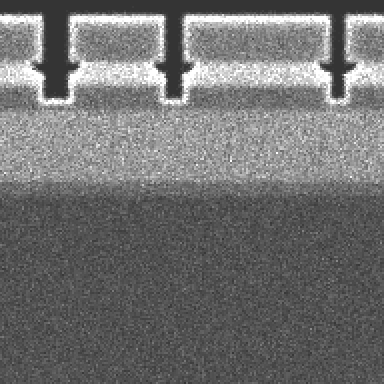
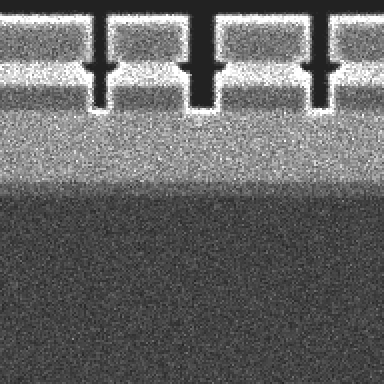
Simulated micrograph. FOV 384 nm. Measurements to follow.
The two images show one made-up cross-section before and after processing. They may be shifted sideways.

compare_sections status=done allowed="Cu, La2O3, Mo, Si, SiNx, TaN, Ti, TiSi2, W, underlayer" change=removed material="SiNx"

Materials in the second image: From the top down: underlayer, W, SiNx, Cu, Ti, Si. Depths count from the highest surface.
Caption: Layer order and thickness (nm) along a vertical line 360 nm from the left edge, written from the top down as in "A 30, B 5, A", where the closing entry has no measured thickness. underlayer 46, W 24, SiNx 24, Cu 72, Ti 14, Si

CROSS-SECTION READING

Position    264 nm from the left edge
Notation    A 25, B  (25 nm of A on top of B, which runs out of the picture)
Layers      underlayer 46, W 24, SiNx 24, Cu 72, Ti 14, Si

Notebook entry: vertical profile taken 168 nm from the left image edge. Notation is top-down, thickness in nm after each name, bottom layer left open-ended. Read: underlayer 46, W 24, SiNx 24, Cu 72, Ti 14, Si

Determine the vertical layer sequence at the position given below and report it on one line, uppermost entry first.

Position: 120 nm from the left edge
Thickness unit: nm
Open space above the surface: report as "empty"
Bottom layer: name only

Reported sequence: underlayer 46, W 24, SiNx 24, Cu 72, Ti 14, Si